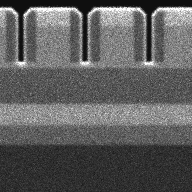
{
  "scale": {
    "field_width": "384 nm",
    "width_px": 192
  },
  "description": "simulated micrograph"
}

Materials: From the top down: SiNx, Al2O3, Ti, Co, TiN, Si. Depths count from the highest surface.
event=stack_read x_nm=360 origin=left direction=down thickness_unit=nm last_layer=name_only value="Co 36, Al2O3 84, Ti 72, Co 42, TiN 40, Si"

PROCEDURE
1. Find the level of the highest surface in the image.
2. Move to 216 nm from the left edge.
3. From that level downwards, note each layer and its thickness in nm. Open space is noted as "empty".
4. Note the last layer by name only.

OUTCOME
Co 36, Al2O3 84, Ti 72, Co 42, TiN 40, Si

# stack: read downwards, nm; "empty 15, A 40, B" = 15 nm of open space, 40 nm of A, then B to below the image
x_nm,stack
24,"empty 2, SiNx 106, Al2O3 12, Ti 72, Co 42, TiN 40, Si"